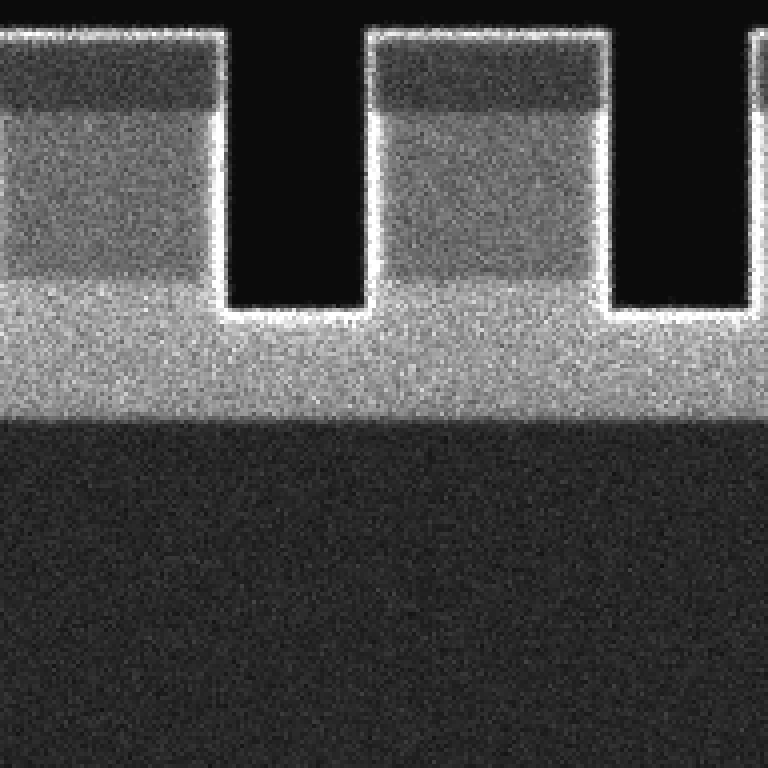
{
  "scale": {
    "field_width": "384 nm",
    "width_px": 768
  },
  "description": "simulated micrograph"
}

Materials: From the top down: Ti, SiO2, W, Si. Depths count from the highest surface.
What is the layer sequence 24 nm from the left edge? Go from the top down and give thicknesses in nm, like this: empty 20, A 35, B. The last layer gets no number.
Ti 40, SiO2 84, W 70, Si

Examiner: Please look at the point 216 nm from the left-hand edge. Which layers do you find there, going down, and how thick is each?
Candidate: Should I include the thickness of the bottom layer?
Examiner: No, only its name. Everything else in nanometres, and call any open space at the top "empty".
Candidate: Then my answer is Ti 40, SiO2 84, W 70, Si